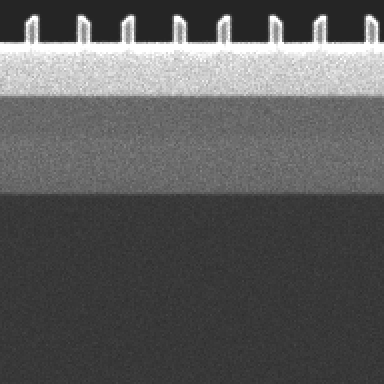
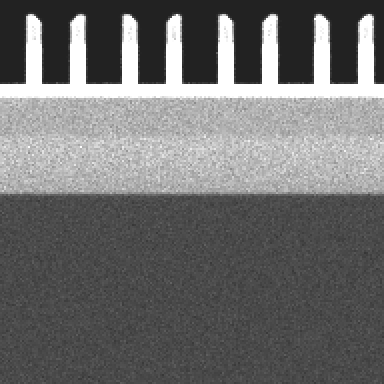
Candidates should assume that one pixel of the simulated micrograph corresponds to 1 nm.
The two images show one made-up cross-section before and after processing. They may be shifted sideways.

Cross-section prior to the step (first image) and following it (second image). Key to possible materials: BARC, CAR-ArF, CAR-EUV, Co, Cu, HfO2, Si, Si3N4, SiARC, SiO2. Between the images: HfO2 was removed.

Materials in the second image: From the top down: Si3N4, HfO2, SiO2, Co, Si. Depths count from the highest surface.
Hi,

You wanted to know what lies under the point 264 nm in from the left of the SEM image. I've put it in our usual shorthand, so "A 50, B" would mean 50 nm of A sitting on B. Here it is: empty 6, Si3N4 22, HfO2 52, SiO2 40, Co 58, Si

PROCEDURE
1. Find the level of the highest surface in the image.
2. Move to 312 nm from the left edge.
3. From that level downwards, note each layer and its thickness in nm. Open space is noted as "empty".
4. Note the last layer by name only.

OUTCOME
empty 70, HfO2 10, SiO2 40, Co 58, Si